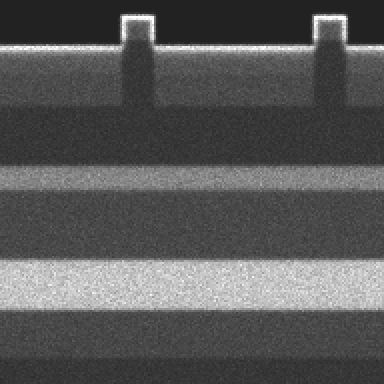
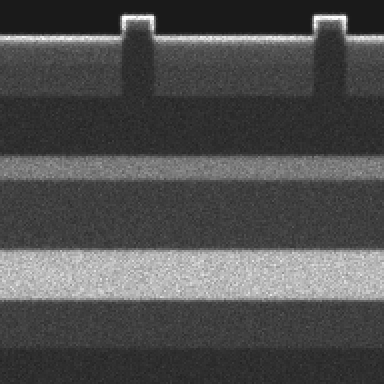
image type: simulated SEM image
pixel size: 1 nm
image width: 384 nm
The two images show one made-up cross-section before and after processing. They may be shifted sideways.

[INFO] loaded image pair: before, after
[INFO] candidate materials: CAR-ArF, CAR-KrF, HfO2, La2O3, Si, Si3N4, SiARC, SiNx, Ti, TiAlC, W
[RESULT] removed Si3N4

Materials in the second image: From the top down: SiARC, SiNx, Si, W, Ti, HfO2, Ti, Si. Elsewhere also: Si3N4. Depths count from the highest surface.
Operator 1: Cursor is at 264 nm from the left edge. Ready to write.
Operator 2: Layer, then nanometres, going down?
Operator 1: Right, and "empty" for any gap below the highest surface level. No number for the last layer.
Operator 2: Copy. empty 20, SiARC 28, SiNx 32, Si 60, W 24, Ti 70, HfO2 50, Ti 48, Si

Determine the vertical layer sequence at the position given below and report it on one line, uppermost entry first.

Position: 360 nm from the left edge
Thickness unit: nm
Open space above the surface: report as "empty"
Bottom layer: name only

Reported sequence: empty 20, SiARC 28, SiNx 32, Si 60, W 24, Ti 70, HfO2 50, Ti 48, Si